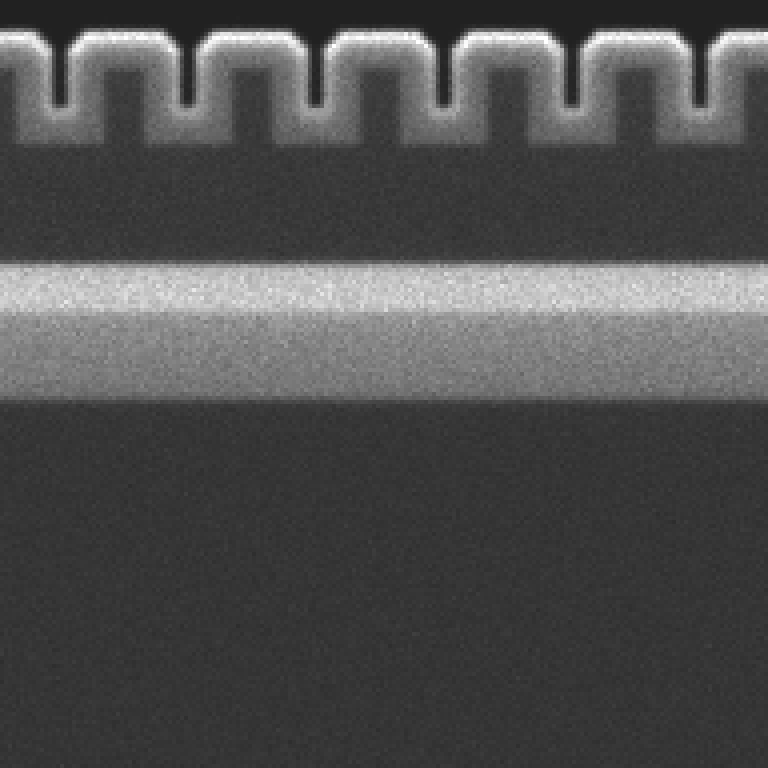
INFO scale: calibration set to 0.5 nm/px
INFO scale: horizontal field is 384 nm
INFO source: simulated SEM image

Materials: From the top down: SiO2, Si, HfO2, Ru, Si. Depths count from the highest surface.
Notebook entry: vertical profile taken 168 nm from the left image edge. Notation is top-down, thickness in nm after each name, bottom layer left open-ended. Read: empty 2, SiO2 54, Si 60, HfO2 24, Ru 44, Si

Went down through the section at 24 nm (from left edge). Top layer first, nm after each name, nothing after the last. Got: empty 8, SiO2 48, Si 60, HfO2 24, Ru 44, Si